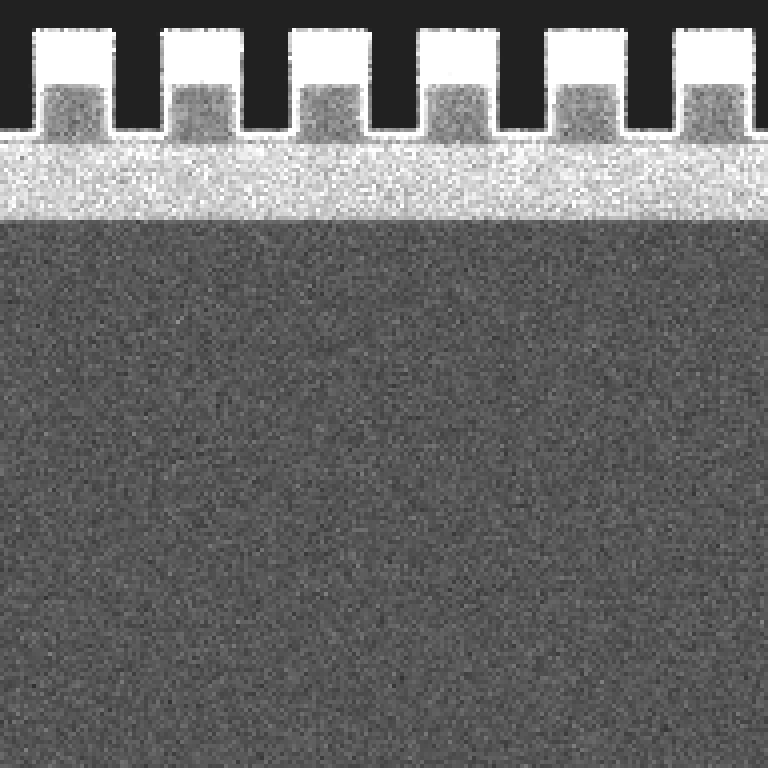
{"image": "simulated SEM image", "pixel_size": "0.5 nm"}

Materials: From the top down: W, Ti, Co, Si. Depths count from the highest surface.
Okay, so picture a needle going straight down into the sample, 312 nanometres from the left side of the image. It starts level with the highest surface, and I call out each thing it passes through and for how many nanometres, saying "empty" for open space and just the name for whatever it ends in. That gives empty 50, Ti 6, Co 38, Si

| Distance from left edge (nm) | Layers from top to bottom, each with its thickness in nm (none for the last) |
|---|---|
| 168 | W 26, Ti 30, Co 38, Si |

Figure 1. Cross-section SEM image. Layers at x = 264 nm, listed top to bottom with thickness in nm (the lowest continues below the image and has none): empty 50, Ti 6, Co 38, Si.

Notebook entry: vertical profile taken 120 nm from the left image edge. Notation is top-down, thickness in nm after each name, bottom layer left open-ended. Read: empty 50, Ti 6, Co 38, Si